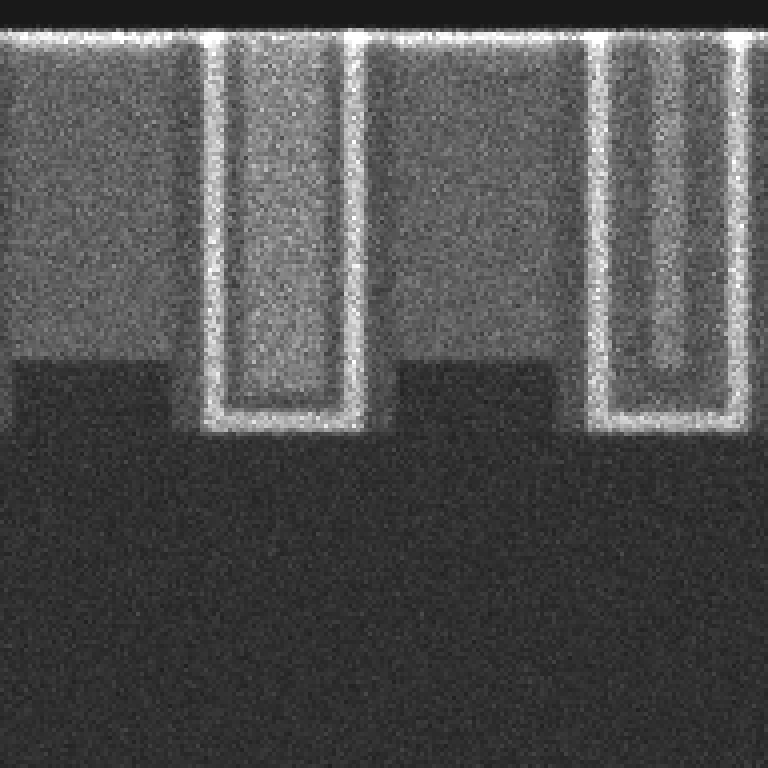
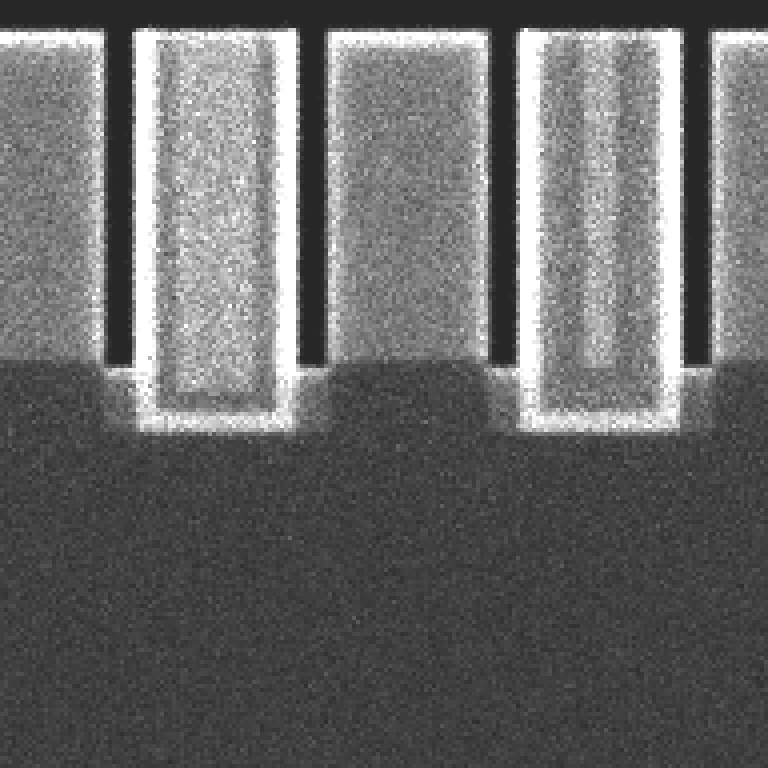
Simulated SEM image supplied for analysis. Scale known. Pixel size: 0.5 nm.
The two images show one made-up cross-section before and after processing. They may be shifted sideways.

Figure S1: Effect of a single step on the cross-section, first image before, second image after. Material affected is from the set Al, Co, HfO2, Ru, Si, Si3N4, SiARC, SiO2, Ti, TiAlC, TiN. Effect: removed Si3N4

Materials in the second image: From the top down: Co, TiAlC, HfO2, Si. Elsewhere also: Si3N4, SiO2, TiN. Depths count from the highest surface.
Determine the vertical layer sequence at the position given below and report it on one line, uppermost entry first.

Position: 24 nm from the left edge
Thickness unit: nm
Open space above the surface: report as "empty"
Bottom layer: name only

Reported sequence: SiO2 164, Si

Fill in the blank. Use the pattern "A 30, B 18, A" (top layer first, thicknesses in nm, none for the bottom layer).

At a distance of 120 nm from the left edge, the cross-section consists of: Co 180, TiAlC 10, HfO2 10, Si